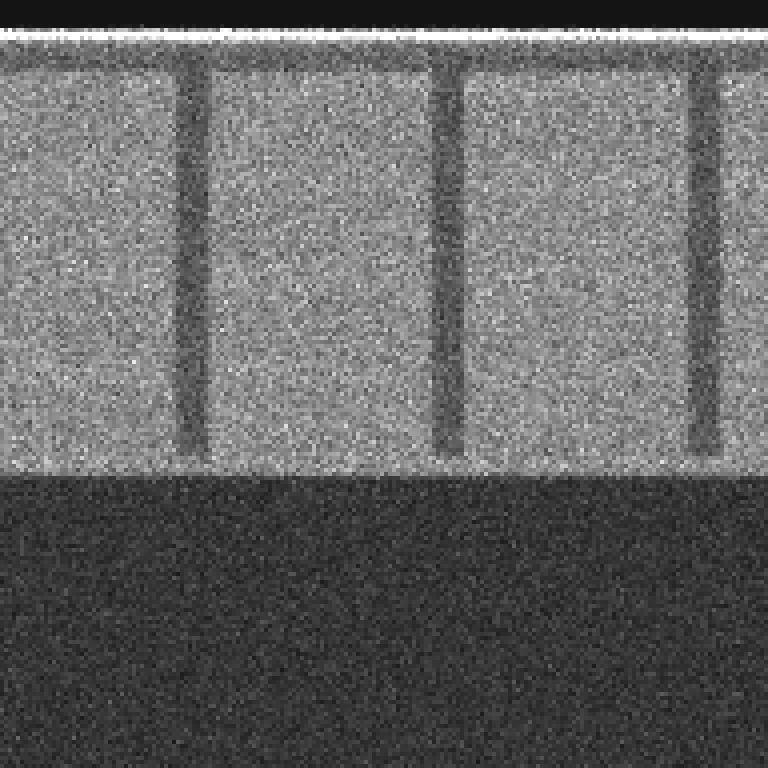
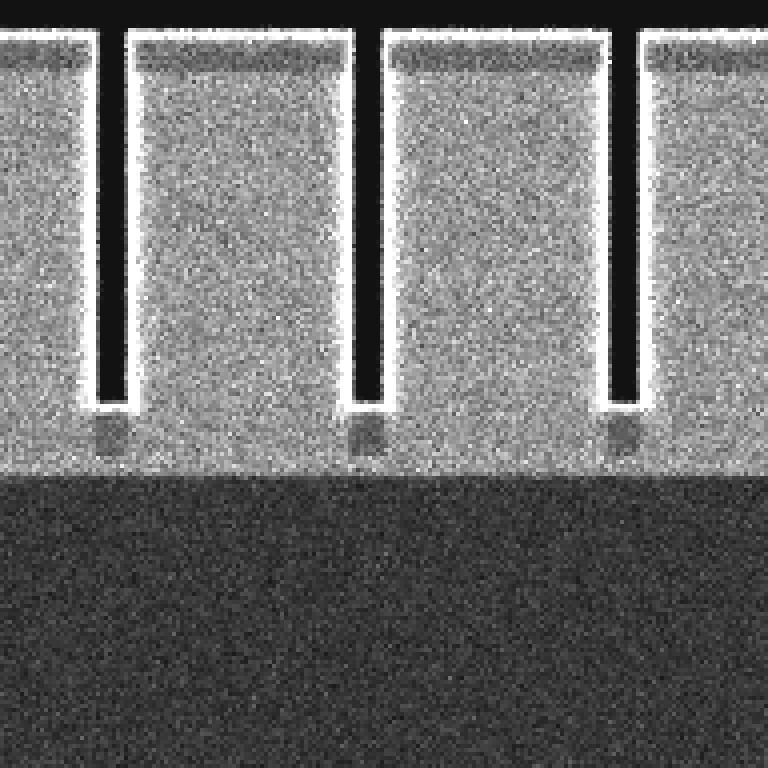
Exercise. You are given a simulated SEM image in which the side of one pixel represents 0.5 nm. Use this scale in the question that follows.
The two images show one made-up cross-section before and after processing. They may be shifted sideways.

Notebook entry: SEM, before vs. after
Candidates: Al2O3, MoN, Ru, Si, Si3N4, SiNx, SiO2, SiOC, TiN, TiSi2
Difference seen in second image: SiNx removed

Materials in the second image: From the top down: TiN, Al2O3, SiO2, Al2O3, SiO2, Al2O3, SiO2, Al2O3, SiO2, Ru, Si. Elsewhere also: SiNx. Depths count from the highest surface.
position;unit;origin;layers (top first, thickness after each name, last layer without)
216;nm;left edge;TiN 20, Al2O3 12, SiO2 36, Al2O3 12, SiO2 36, Al2O3 12, SiO2 36, Al2O3 12, SiO2 36, Ru 10, Si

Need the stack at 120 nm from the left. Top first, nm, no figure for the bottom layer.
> TiN 20, Al2O3 12, SiO2 36, Al2O3 12, SiO2 36, Al2O3 12, SiO2 36, Al2O3 12, SiO2 36, Ru 10, Si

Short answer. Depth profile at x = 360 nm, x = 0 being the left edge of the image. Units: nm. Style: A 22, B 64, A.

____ TiN 20, Al2O3 12, SiO2 36, Al2O3 12, SiO2 36, Al2O3 12, SiO2 36, Al2O3 12, SiO2 36, Ru 10, Si